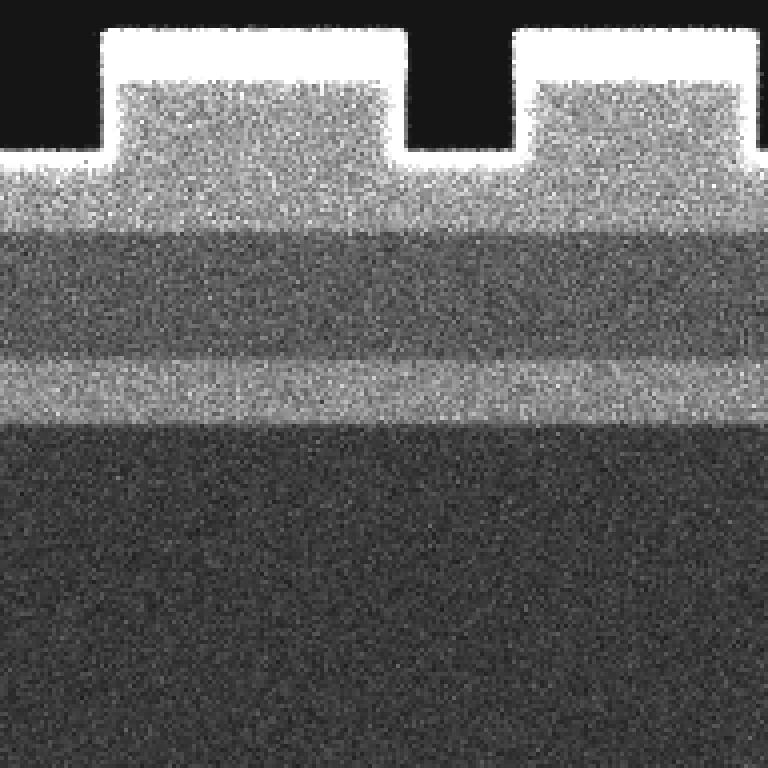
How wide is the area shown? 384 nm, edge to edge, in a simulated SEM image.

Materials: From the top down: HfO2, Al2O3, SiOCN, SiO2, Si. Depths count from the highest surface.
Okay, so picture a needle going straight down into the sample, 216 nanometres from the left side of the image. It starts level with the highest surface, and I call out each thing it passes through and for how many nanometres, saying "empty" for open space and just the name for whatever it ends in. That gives empty 60, Al2O3 40, SiOCN 64, SiO2 32, Si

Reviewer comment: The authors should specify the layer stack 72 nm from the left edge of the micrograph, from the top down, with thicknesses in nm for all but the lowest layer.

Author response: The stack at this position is HfO2 24, Al2O3 76, SiOCN 64, SiO2 32, Si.